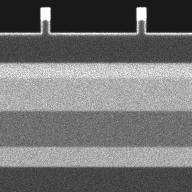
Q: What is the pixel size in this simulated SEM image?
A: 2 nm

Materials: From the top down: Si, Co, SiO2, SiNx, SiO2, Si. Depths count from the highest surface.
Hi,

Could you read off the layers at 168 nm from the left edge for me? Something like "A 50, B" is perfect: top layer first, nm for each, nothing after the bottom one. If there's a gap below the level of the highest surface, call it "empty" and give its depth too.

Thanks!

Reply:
empty 50, Si 60, Co 30, SiO2 66, SiNx 72, SiO2 40, Si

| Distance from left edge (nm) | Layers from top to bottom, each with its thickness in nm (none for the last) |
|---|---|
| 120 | empty 50, Si 60, Co 30, SiO2 66, SiNx 72, SiO2 40, Si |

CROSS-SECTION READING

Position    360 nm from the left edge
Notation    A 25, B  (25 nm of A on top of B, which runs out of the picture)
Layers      empty 50, Si 60, Co 30, SiO2 66, SiNx 72, SiO2 40, Si